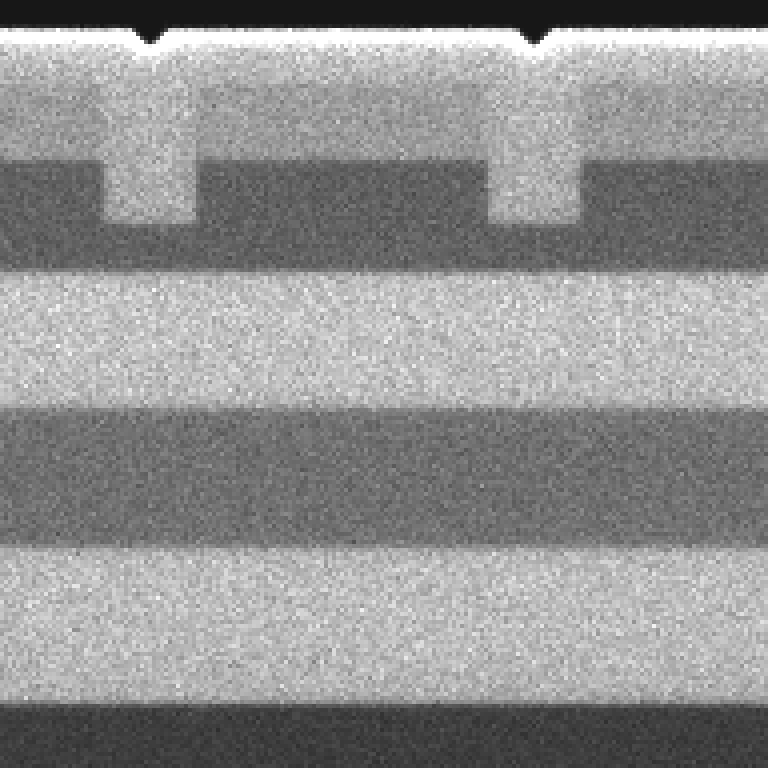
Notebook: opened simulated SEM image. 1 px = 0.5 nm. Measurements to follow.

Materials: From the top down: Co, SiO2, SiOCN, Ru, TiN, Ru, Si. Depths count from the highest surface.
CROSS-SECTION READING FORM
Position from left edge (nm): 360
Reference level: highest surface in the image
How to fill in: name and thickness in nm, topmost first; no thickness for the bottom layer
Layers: Co 26, SiO2 38, SiOCN 56, Ru 68, TiN 70, Ru 78, Si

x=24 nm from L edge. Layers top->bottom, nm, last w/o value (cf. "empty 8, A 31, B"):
Co 26, SiO2 38, SiOCN 56, Ru 68, TiN 70, Ru 78, Si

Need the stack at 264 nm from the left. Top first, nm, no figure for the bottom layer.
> empty 8, Co 88, SiOCN 24, Ru 68, TiN 70, Ru 78, Si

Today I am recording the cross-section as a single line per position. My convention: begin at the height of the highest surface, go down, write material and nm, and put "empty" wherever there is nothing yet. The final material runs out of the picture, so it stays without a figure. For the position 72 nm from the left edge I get empty 8, Co 88, SiOCN 24, Ru 68, TiN 70, Ru 78, Si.